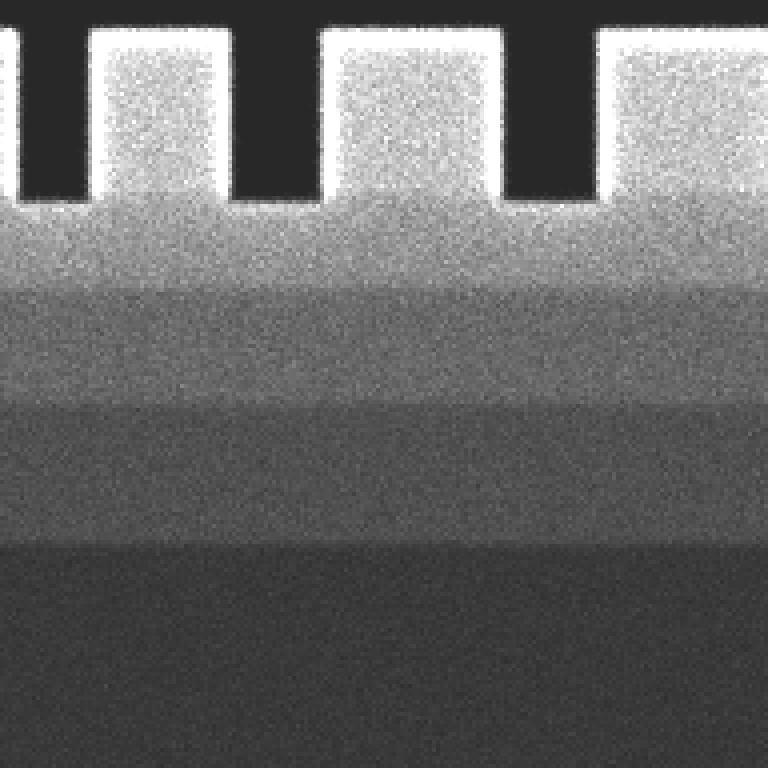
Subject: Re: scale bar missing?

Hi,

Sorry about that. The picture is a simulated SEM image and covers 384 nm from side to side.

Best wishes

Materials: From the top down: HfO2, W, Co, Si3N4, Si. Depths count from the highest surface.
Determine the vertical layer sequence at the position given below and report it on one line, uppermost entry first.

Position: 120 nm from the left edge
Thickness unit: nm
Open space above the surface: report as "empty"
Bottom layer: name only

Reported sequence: empty 86, W 42, Co 58, Si3N4 70, Si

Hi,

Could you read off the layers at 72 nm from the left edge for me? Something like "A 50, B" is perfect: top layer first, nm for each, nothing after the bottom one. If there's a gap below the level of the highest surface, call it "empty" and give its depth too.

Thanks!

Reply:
HfO2 80, W 48, Co 58, Si3N4 70, Si